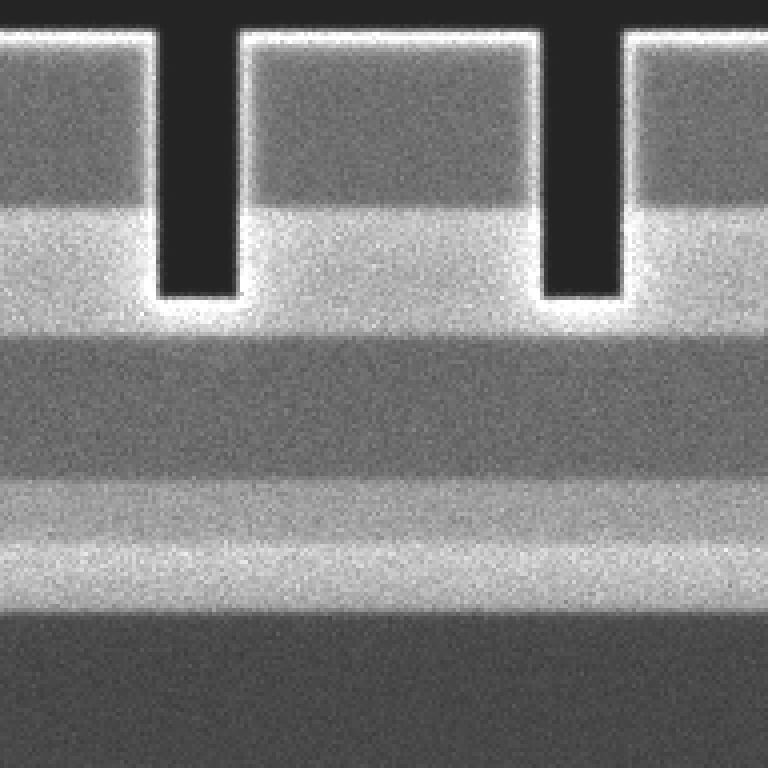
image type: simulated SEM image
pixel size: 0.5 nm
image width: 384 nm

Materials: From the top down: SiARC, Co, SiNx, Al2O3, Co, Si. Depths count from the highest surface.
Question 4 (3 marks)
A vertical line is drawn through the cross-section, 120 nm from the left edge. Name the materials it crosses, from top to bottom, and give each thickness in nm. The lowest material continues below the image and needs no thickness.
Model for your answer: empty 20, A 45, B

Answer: SiARC 88, Co 64, SiNx 72, Al2O3 32, Co 34, Si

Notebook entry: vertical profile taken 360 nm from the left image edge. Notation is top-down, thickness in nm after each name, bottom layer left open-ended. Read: SiARC 88, Co 64, SiNx 72, Al2O3 32, Co 34, Si